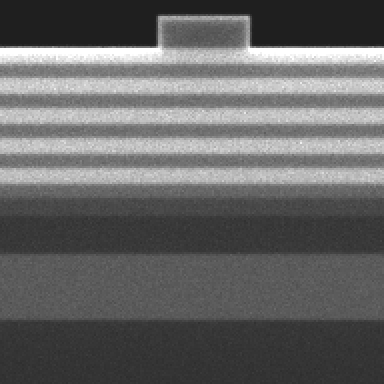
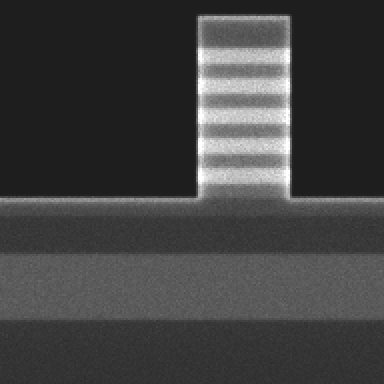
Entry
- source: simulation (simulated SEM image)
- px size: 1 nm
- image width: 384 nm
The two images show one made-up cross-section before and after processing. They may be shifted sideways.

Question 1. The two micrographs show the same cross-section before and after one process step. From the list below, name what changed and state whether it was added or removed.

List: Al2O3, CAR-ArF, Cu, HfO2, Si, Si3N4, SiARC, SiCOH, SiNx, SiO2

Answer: Al2O3 and HfO2, removed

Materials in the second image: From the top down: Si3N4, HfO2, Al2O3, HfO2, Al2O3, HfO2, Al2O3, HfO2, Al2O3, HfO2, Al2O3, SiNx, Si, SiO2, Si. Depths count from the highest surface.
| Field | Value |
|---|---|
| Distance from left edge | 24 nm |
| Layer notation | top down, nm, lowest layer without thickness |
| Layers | empty 182, SiNx 18, Si 38, SiO2 66, Si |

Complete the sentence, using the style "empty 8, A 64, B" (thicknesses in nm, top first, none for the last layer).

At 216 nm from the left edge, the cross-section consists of Si3N4 32, HfO2 16, Al2O3 14, HfO2 16, Al2O3 14, HfO2 16, Al2O3 14, HfO2 16, Al2O3 14, HfO2 16, Al2O3 14, SiNx 18, Si 38, SiO2 66, Si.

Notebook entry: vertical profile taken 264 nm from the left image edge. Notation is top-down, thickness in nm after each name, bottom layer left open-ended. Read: Si3N4 32, HfO2 16, Al2O3 14, HfO2 16, Al2O3 14, HfO2 16, Al2O3 14, HfO2 16, Al2O3 14, HfO2 16, Al2O3 14, SiNx 18, Si 38, SiO2 66, Si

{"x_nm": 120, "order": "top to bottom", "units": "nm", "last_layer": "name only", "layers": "empty 182, SiNx 18, Si 38, SiO2 66, Si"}